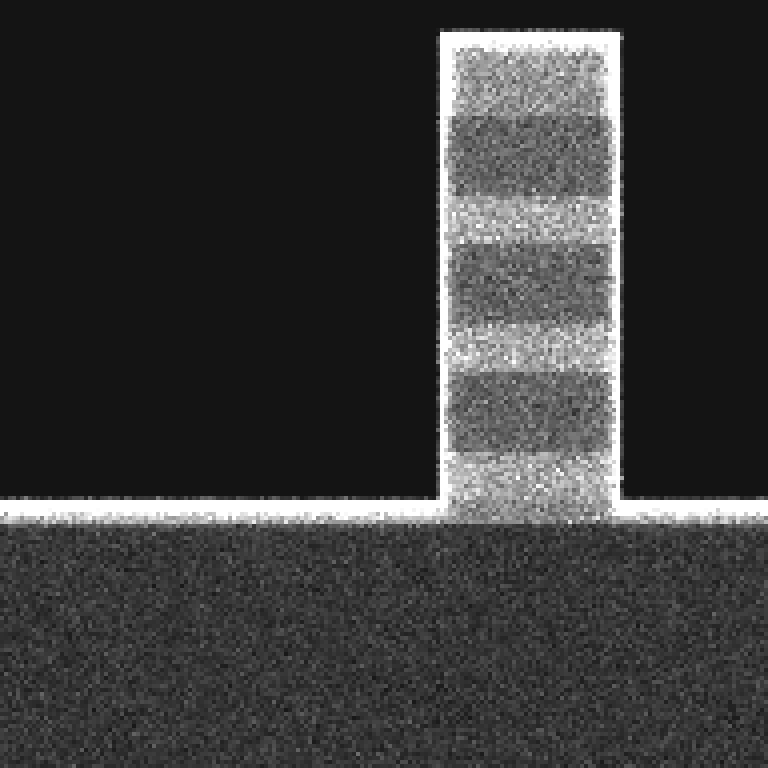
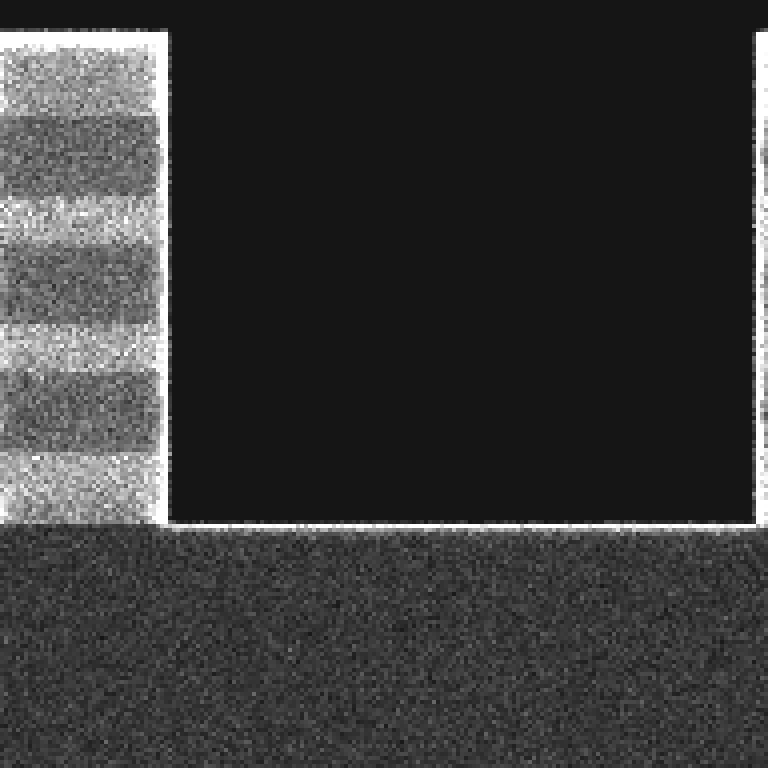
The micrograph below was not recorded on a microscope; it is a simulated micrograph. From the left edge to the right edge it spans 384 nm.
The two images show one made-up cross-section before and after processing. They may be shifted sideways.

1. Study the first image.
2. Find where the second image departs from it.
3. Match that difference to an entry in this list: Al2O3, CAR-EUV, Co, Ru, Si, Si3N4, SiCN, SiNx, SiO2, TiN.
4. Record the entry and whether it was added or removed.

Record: SiO2 / removed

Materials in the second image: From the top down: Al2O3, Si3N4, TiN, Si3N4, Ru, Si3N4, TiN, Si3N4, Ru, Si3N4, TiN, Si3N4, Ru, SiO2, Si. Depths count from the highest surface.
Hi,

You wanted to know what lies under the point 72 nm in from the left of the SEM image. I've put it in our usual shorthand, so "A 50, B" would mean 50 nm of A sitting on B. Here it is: Al2O3 42, Si3N4 14, TiN 12, Si3N4 14, Ru 24, Si3N4 14, TiN 12, Si3N4 14, Ru 24, Si3N4 14, TiN 12, Si3N4 14, Ru 24, SiO2 12, Si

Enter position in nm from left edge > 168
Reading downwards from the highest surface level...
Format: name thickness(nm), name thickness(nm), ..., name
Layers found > empty 246, Si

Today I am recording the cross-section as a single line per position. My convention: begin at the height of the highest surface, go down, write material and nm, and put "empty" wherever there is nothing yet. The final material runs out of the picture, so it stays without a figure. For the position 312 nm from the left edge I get empty 246, Si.